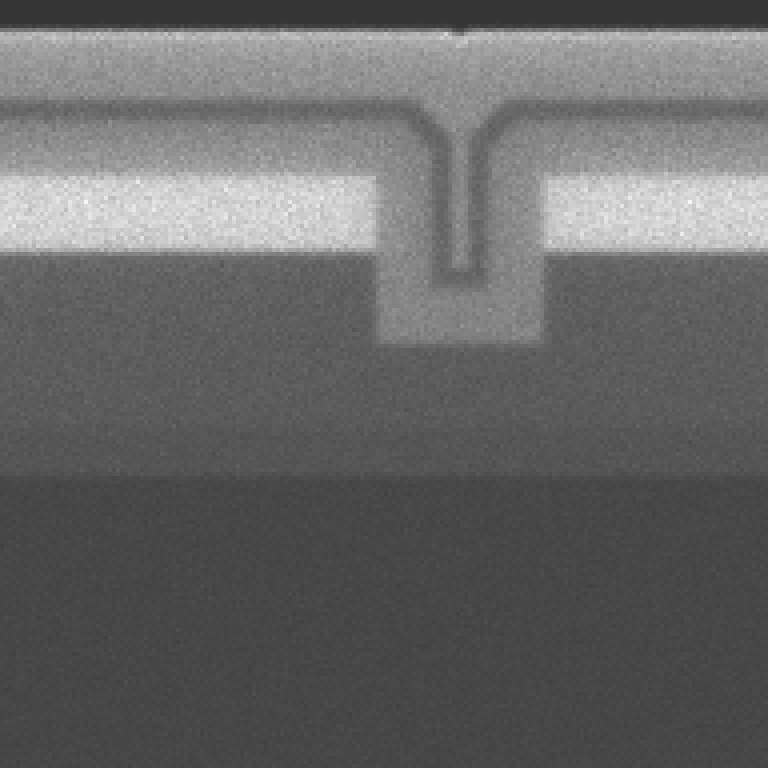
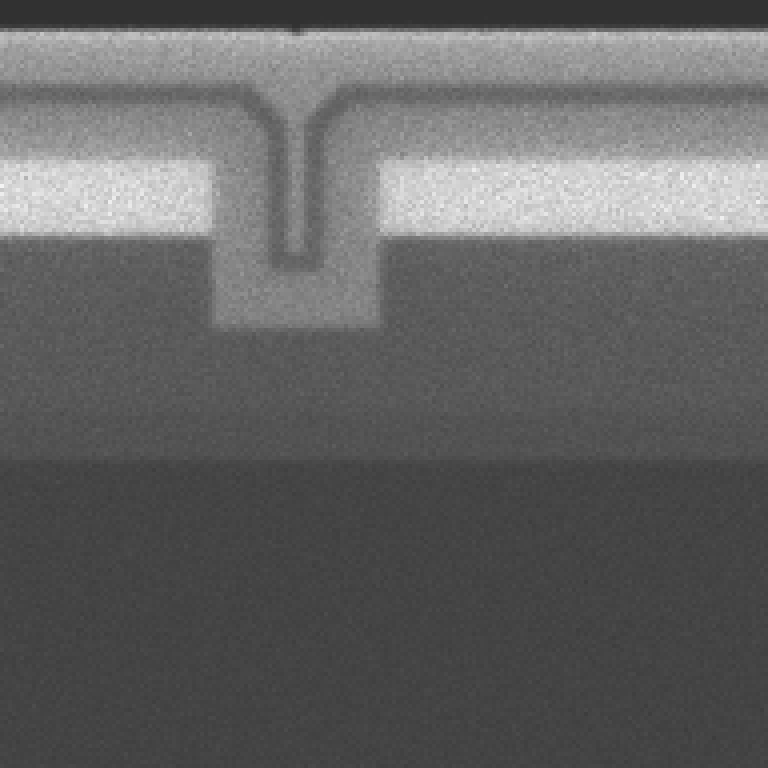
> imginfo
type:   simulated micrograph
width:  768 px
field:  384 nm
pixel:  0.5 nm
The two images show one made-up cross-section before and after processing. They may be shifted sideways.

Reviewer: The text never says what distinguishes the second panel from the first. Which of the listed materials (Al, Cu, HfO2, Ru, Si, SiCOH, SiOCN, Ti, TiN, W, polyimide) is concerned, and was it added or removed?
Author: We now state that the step removed W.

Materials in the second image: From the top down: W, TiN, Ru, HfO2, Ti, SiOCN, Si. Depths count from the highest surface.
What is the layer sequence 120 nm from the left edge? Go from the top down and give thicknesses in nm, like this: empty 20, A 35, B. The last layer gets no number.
W 26, TiN 12, Ru 110, Ti 42, SiOCN 24, Si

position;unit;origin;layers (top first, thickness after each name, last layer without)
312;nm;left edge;W 26, TiN 10, Ru 28, HfO2 38, Ti 88, SiOCN 24, Si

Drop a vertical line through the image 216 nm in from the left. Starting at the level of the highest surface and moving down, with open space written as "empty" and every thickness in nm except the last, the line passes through W 26, TiN 10, Ru 28, HfO2 38, Ti 88, SiOCN 24, Si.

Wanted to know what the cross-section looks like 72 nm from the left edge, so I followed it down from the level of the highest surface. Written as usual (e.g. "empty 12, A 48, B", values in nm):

W 26, TiN 10, Ru 28, HfO2 38, Ti 88, SiOCN 24, Si